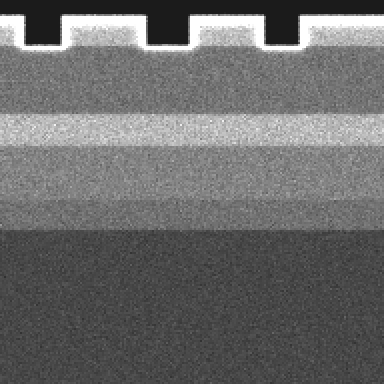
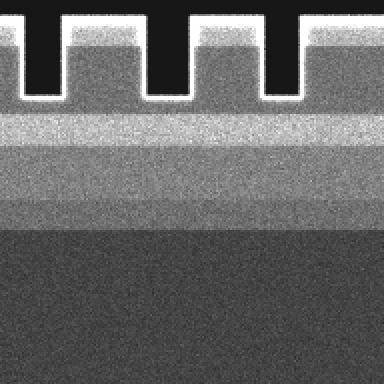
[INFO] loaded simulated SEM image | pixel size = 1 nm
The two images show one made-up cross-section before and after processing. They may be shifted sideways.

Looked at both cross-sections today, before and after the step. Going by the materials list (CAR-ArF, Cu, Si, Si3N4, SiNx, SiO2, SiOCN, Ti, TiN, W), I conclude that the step removed SiNx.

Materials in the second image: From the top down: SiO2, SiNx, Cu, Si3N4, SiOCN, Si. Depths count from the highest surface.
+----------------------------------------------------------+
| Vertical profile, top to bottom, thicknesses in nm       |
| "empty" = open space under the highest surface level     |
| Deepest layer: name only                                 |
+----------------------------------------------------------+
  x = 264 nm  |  empty 80, SiNx 18, Cu 32, Si3N4 54, SiOCN 30, Si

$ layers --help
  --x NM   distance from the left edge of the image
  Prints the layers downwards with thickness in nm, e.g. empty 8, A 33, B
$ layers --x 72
SiO2 30, SiNx 68, Cu 32, Si3N4 54, SiOCN 30, Si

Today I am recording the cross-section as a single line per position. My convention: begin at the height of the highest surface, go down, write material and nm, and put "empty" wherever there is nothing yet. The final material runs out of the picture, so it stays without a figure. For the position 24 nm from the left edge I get empty 80, SiNx 18, Cu 32, Si3N4 54, SiOCN 30, Si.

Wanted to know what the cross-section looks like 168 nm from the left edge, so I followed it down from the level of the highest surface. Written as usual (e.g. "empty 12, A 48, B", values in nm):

empty 80, SiNx 18, Cu 32, Si3N4 54, SiOCN 30, Si